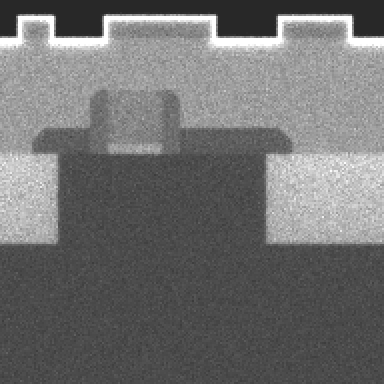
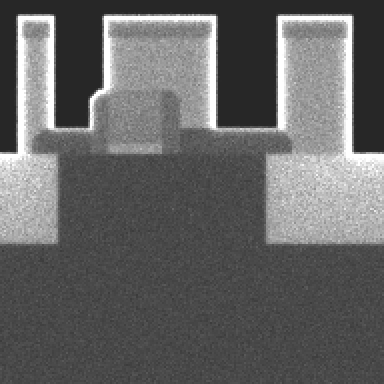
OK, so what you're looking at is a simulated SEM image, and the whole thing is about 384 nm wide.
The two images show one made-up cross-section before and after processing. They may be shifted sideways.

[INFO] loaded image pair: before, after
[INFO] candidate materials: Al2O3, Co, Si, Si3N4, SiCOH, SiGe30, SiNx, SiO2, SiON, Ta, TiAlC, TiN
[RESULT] removed SiO2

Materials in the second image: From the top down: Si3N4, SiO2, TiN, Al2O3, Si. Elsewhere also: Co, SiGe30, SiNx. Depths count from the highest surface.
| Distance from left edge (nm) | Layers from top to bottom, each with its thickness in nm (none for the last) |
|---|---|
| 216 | empty 112, SiGe30 26, Si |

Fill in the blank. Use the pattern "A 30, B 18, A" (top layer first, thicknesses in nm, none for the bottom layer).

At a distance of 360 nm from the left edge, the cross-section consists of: empty 138, Co 90, Si